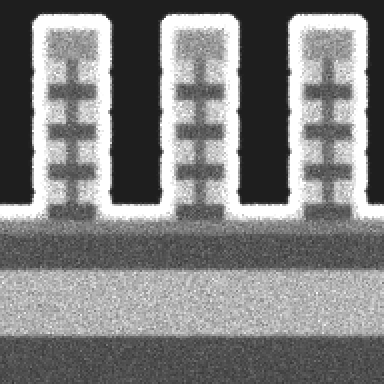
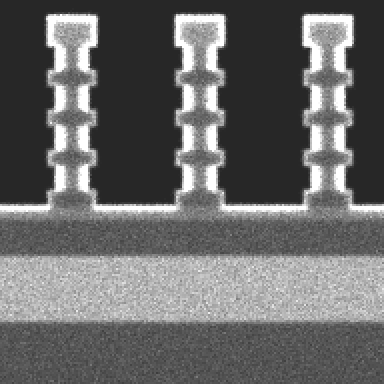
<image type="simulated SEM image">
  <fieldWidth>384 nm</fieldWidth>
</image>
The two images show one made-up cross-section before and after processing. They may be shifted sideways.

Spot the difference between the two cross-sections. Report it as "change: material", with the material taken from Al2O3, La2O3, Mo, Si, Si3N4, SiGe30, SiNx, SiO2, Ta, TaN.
removed: Al2O3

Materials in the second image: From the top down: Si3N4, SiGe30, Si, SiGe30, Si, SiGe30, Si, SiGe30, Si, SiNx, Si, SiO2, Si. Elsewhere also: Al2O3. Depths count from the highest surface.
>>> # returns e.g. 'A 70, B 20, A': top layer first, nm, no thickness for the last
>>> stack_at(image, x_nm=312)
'Si3N4 30, Al2O3 24, Si 16, Al2O3 24, Si 16, Al2O3 24, Si 16, Al2O3 24, Si 16, SiNx 14, Si 36, SiO2 66, Si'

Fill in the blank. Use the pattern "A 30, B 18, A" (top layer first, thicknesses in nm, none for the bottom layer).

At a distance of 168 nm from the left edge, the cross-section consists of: empty 190, SiNx 14, Si 36, SiO2 66, Si